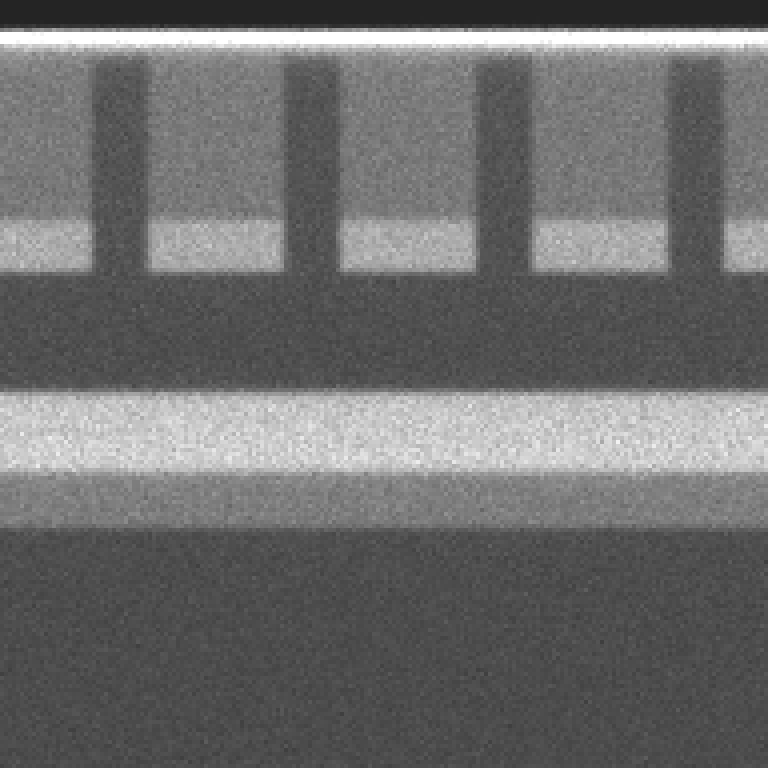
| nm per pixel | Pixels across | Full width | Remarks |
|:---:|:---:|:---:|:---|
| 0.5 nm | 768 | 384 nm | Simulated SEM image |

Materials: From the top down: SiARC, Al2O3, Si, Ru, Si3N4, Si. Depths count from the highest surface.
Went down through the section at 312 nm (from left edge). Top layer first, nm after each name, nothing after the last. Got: SiARC 94, Al2O3 26, Si 60, Ru 40, Si3N4 28, Si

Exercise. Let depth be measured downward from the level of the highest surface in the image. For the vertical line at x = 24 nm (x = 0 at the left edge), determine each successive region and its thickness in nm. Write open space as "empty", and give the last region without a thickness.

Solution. SiARC 94, Al2O3 26, Si 60, Ru 40, Si3N4 28, Si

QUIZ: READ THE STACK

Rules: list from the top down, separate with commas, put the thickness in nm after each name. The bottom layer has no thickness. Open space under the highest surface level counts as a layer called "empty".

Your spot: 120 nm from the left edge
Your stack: SiARC 94, Al2O3 26, Si 60, Ru 40, Si3N4 28, Si